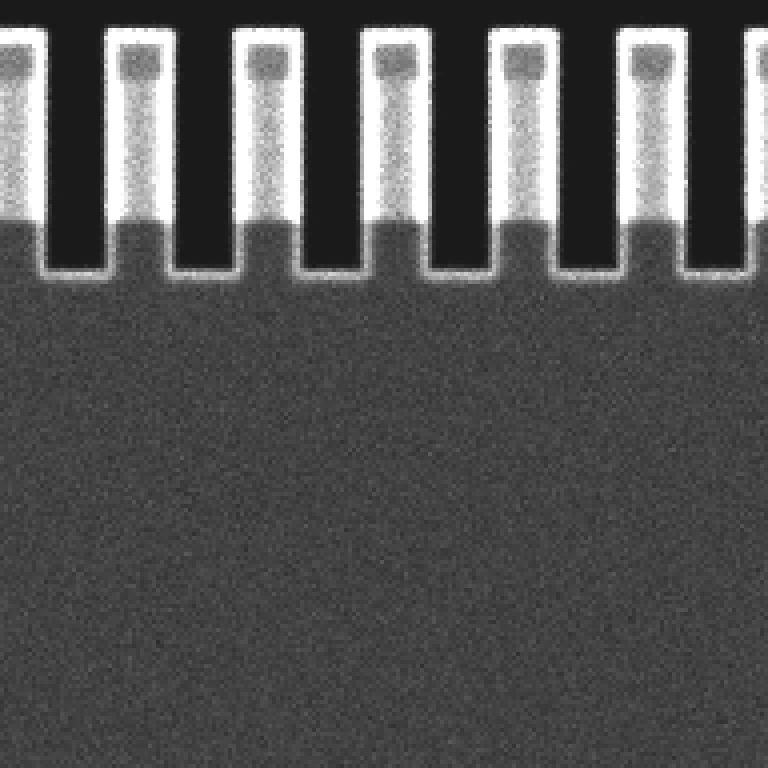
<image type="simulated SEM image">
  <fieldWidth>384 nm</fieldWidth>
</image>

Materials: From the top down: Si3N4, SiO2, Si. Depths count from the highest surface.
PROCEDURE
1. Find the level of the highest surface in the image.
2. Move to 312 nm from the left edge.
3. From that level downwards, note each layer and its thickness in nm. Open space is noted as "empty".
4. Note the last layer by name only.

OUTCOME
Si3N4 24, SiO2 70, Si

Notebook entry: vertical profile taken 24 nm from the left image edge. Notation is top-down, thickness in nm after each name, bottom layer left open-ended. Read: empty 120, Si